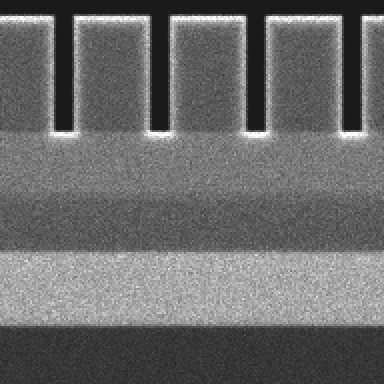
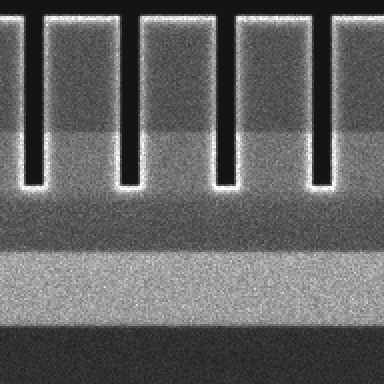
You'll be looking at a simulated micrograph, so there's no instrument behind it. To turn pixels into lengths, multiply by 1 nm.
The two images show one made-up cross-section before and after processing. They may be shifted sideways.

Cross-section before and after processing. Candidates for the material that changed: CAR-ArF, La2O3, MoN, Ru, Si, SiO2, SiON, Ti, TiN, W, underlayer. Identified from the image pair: SiO2 (removed).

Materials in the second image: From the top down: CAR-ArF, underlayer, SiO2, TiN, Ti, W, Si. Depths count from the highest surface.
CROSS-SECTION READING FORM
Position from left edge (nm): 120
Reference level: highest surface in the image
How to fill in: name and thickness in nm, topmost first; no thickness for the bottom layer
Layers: empty 170, SiO2 6, TiN 8, Ti 52, W 74, Si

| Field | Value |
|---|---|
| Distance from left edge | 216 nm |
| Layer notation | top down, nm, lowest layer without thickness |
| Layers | empty 170, SiO2 6, TiN 8, Ti 52, W 74, Si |